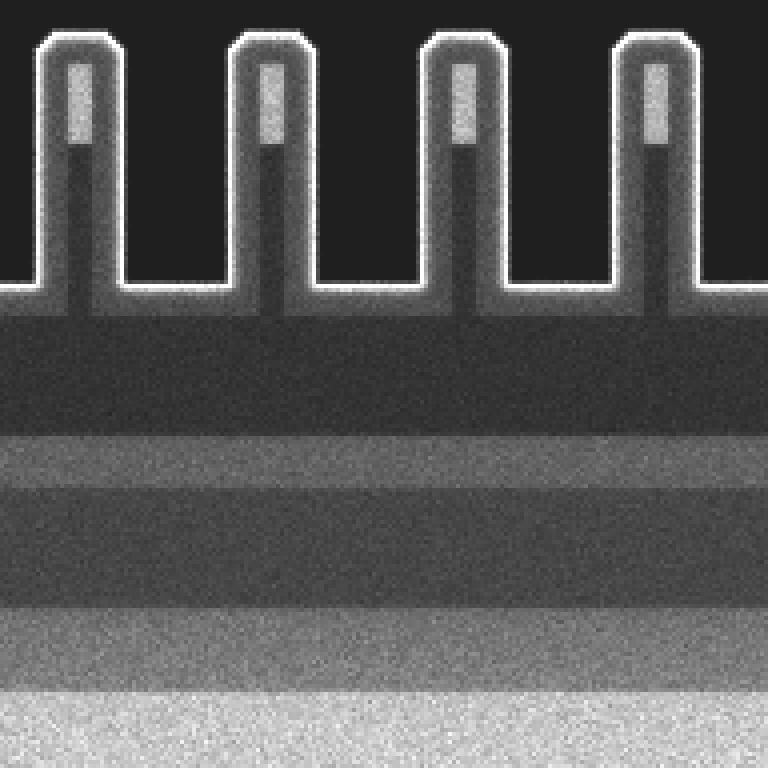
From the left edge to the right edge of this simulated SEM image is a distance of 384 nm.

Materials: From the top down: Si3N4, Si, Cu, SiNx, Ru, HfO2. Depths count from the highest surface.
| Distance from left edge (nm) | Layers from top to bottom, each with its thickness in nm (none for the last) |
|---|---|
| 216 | empty 2, Si3N4 140, Si 60, Cu 26, SiNx 60, Ru 42, HfO2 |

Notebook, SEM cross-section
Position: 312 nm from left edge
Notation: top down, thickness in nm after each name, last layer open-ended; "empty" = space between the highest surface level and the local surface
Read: empty 2, Si3N4 140, Si 60, Cu 26, SiNx 60, Ru 42, HfO2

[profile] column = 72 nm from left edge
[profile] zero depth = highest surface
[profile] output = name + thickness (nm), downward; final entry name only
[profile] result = empty 126, Si3N4 16, Si 60, Cu 26, SiNx 60, Ru 42, HfO2